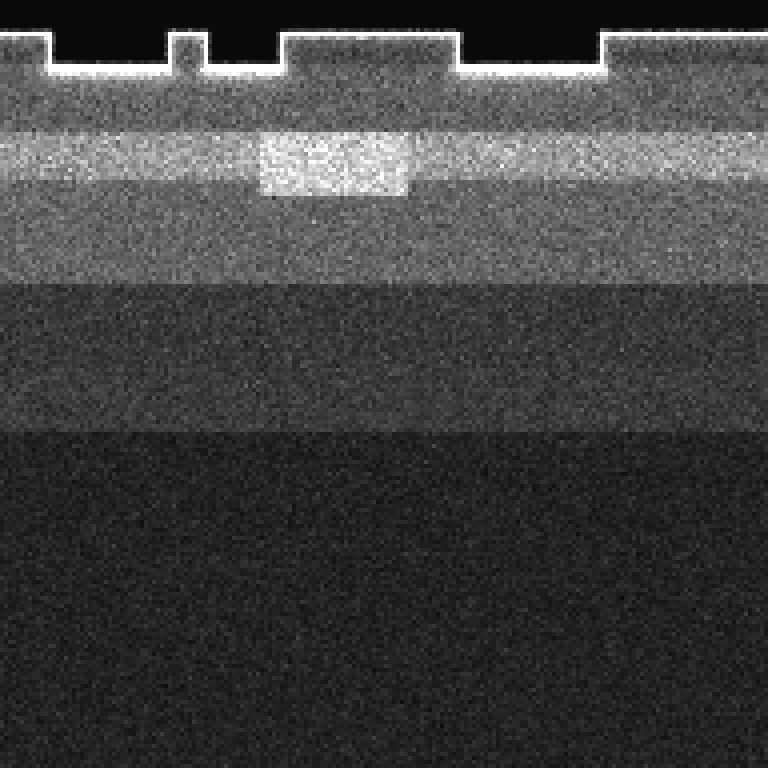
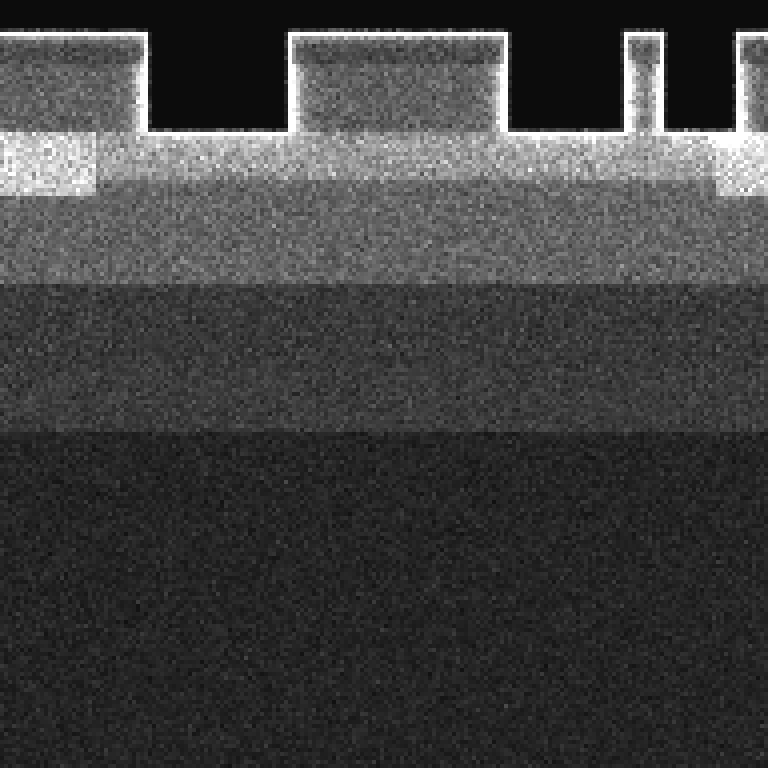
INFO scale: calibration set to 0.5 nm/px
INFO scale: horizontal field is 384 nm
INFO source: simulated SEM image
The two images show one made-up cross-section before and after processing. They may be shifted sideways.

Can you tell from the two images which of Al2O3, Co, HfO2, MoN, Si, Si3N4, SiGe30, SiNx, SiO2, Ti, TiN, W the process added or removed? Yes, it removed SiO2.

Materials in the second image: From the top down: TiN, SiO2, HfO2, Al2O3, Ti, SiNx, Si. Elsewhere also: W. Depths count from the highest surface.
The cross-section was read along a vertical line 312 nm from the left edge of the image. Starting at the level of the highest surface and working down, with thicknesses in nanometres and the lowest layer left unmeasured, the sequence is TiN 16, SiO2 34, W 24, Al2O3 52, Ti 42, SiNx 32, Si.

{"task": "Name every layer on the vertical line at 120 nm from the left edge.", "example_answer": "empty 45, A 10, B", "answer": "empty 50, W 24, Al2O3 52, Ti 42, SiNx 32, Si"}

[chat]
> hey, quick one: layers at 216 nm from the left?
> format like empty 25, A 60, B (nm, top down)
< TiN 16, SiO2 34, W 24, Al2O3 52, Ti 42, SiNx 32, Si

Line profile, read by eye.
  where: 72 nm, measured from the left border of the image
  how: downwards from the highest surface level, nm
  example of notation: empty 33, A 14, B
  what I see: TiN 16, SiO2 34, W 24, Al2O3 52, Ti 42, SiNx 32, Si